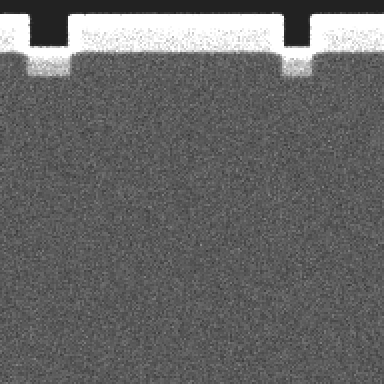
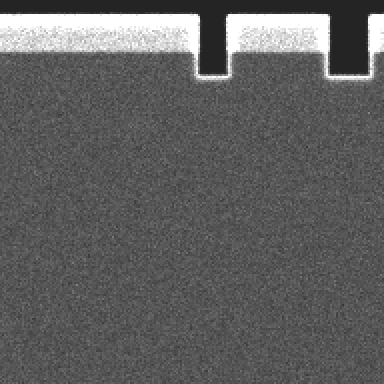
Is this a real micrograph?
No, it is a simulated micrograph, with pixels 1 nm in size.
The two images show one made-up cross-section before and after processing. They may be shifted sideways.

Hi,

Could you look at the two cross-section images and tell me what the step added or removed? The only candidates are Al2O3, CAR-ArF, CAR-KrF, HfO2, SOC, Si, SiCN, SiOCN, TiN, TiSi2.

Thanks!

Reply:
removed SOC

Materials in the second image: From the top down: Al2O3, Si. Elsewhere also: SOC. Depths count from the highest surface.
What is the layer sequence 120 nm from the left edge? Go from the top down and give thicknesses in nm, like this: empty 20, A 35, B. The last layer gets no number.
Al2O3 36, Si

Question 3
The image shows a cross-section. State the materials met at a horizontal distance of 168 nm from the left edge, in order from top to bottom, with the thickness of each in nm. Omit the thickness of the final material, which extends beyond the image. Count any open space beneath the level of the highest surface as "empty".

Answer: Al2O3 36, Si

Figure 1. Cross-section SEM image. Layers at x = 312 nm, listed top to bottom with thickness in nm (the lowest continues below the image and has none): Al2O3 36, Si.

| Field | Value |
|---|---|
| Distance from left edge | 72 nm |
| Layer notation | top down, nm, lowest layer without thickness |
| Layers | Al2O3 36, Si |